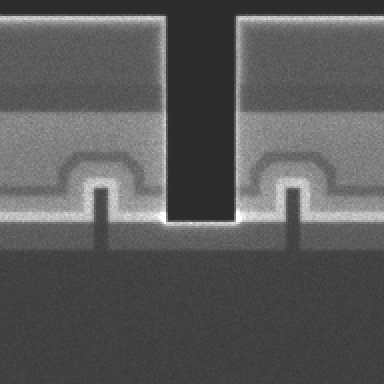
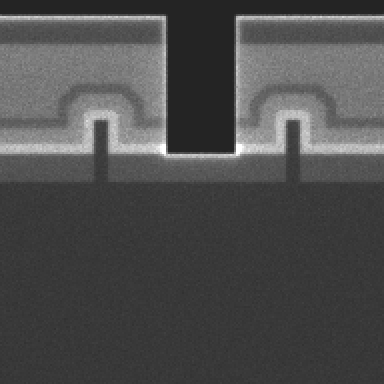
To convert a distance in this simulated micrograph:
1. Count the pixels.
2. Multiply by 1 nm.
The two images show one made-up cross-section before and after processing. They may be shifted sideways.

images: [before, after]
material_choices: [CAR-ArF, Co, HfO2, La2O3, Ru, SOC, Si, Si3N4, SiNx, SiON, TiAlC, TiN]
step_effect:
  removed: SOC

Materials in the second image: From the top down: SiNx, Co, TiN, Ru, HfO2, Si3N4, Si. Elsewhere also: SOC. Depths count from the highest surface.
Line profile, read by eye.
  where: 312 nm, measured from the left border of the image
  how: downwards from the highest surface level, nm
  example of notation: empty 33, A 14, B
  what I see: SiNx 28, Co 40, TiN 10, Ru 50, HfO2 10, Si3N4 28, Si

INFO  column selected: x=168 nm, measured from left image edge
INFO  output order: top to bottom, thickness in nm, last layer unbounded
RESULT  empty 138, Si3N4 28, Si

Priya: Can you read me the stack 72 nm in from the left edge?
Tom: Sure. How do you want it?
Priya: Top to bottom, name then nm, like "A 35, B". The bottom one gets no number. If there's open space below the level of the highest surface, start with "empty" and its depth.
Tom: SiNx 28, Co 42, TiN 16, Ru 42, HfO2 10, Si3N4 28, Si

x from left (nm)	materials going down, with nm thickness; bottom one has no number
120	SiNx 28, Co 40, TiN 10, Ru 50, HfO2 10, Si3N4 28, Si